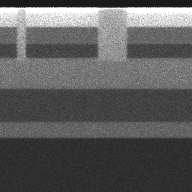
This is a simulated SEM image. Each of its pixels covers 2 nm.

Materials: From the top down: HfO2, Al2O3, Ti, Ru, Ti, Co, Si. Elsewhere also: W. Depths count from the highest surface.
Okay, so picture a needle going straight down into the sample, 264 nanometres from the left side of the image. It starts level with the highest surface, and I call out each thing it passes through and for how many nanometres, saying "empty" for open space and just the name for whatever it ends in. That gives HfO2 38, Al2O3 34, Ti 28, Ru 62, Ti 66, Co 32, Si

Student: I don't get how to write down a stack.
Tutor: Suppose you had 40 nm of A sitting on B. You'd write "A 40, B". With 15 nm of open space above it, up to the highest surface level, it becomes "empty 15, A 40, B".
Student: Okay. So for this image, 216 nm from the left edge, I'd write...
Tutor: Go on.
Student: W 106, Ru 56, Ti 66, Co 32, Si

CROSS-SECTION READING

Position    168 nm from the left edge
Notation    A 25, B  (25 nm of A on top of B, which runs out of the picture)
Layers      HfO2 38, Al2O3 34, Ti 28, Ru 62, Ti 66, Co 32, Si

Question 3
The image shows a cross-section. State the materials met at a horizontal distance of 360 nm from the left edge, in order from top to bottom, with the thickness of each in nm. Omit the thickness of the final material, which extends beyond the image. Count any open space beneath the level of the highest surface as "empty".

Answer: HfO2 38, Al2O3 34, Ti 28, Ru 62, Ti 66, Co 32, Si